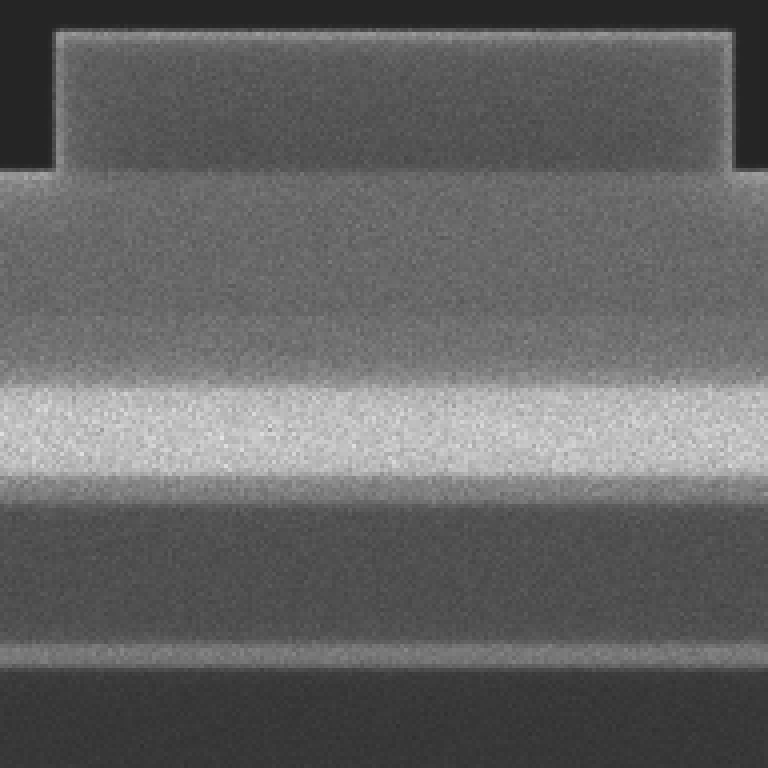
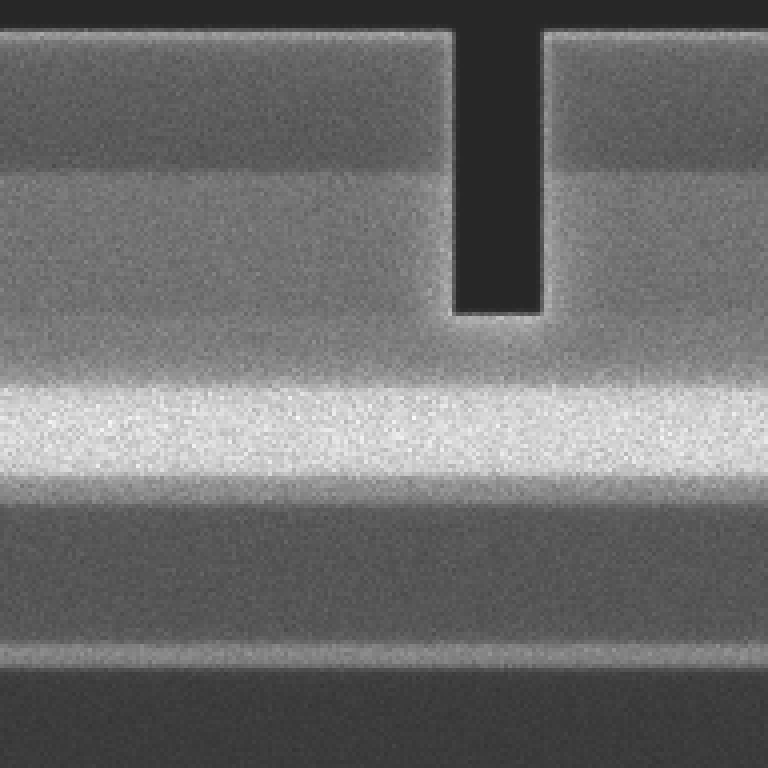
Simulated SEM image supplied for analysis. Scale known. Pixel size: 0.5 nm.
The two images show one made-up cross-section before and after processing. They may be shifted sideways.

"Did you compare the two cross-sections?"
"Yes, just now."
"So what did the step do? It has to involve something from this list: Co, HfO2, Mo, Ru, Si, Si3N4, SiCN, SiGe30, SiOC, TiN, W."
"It removed Ru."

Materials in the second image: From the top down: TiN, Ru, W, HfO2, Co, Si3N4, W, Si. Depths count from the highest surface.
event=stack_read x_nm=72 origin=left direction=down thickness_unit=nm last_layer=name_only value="TiN 70, Ru 72, W 36, HfO2 44, Co 14, Si3N4 70, W 12, Si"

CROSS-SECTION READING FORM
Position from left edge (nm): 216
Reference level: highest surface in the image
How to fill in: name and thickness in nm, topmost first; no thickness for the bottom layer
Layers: TiN 70, Ru 72, W 36, HfO2 44, Co 14, Si3N4 70, W 12, Si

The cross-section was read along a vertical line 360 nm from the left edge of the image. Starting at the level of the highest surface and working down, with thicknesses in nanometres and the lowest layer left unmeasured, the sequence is TiN 70, Ru 72, W 36, HfO2 44, Co 14, Si3N4 70, W 12, Si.